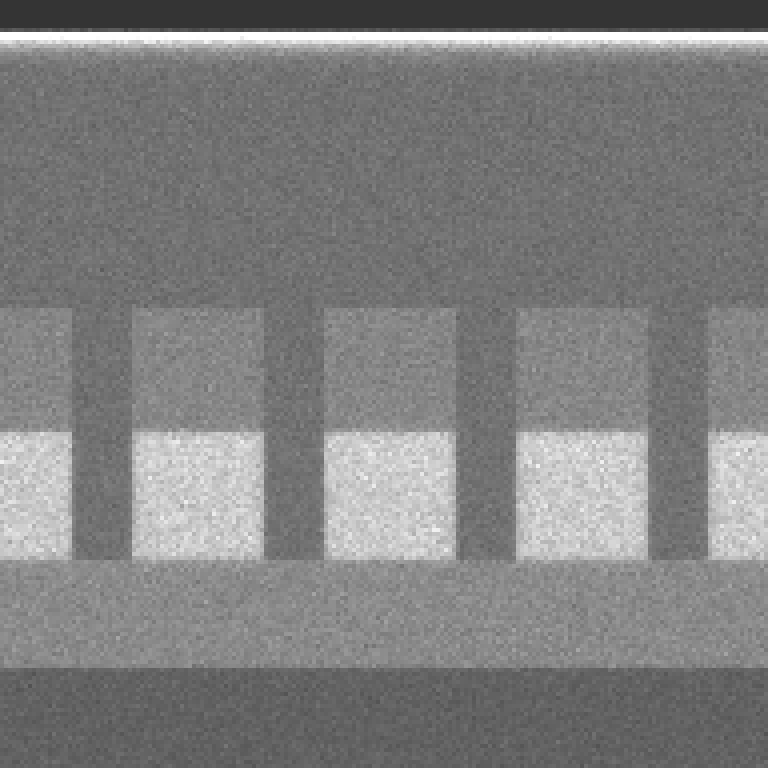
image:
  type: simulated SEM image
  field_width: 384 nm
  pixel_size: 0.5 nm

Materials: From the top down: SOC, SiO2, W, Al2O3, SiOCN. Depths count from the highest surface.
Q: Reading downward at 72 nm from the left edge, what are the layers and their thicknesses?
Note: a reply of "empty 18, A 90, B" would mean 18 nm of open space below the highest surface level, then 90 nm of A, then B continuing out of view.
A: SOC 138, SiO2 62, W 64, Al2O3 54, SiOCN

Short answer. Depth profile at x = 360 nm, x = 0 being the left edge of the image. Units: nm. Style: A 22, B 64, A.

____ SOC 138, SiO2 62, W 64, Al2O3 54, SiOCN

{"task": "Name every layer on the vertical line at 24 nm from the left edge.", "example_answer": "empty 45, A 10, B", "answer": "SOC 138, SiO2 62, W 64, Al2O3 54, SiOCN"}